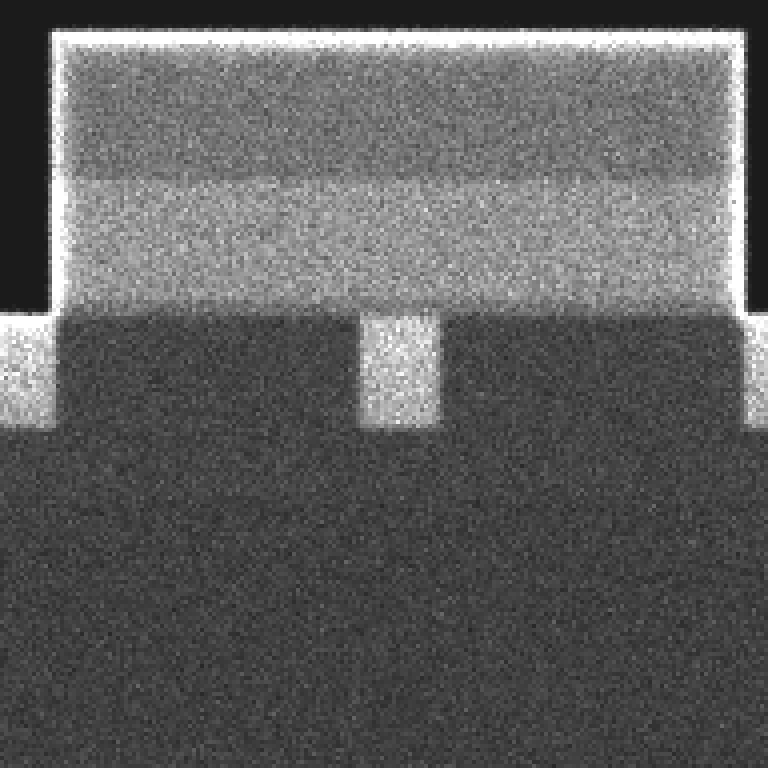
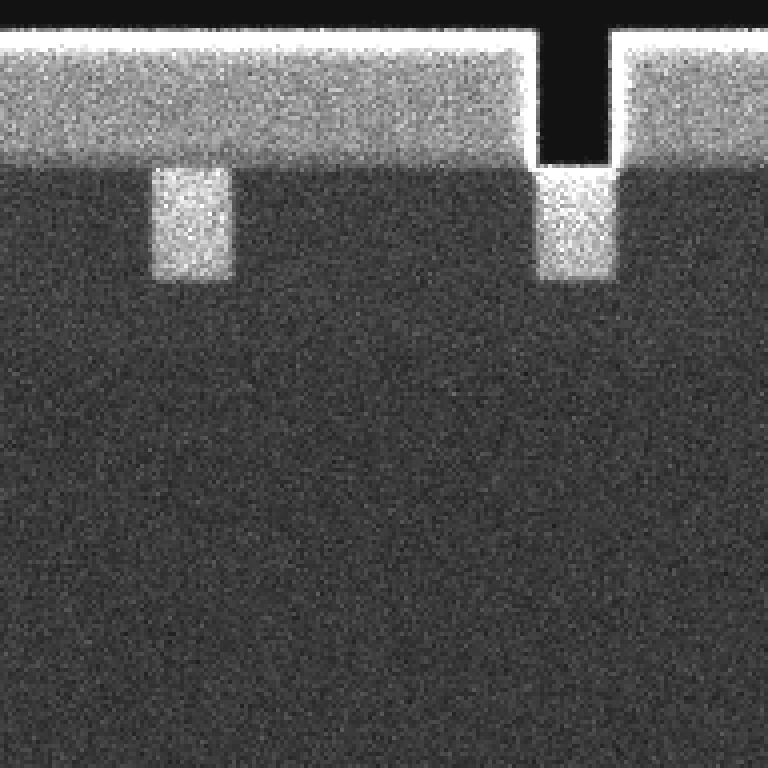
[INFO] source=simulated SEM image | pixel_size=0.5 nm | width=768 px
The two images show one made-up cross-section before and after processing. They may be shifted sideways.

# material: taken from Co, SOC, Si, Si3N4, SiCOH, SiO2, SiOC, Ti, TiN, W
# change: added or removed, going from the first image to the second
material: SOC
change: removed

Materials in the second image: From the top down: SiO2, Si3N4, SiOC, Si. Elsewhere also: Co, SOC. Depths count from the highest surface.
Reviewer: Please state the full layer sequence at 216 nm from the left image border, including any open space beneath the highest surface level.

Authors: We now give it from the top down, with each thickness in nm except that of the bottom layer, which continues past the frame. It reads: SiO2 60, Si3N4 8, SiOC 92, Si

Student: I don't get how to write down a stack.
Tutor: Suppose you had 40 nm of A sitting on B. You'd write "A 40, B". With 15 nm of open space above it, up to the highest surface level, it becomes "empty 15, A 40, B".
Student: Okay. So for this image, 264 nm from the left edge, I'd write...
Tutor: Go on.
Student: SiO2 60, Si3N4 8, SiOC 92, Si